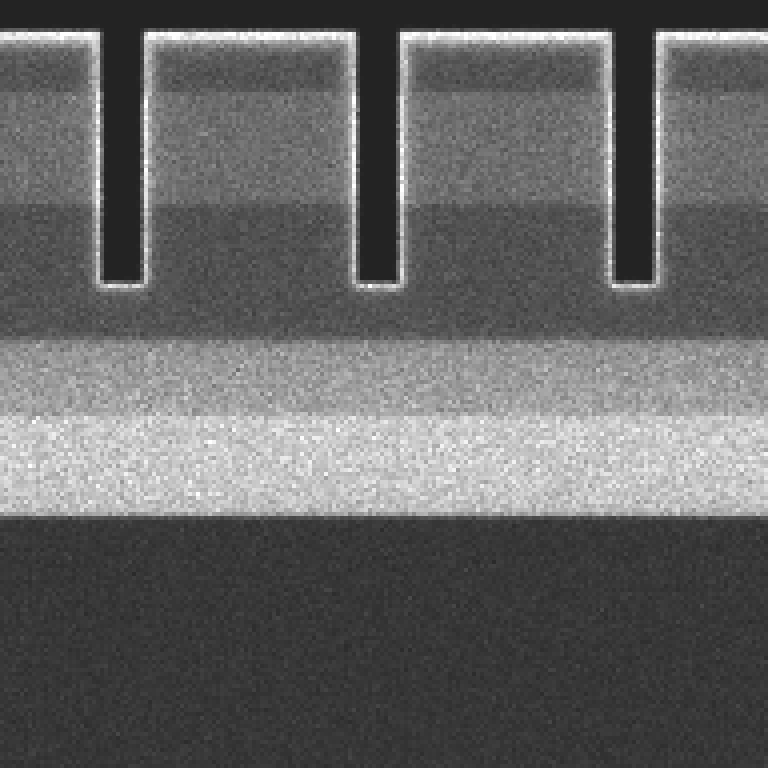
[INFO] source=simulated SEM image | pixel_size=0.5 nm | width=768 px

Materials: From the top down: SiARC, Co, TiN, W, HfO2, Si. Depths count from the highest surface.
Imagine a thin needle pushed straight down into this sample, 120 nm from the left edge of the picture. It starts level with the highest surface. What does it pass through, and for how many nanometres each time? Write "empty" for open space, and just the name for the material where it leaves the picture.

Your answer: SiARC 30, Co 56, TiN 68, W 38, HfO2 50, Si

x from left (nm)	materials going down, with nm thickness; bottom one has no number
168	SiARC 30, Co 56, TiN 68, W 38, HfO2 50, Si